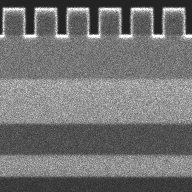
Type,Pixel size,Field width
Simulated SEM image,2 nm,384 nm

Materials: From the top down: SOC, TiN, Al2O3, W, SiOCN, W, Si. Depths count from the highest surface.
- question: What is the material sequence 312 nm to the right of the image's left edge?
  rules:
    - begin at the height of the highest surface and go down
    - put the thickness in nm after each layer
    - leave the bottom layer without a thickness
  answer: empty 54, Al2O3 88, W 90, SiOCN 62, W 44, Si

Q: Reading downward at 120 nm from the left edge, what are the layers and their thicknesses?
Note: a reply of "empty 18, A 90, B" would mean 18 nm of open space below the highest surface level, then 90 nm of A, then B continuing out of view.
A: empty 54, Al2O3 88, W 90, SiOCN 62, W 44, Si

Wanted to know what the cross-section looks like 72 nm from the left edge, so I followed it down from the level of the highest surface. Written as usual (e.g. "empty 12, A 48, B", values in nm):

SOC 14, TiN 40, Al2O3 88, W 90, SiOCN 62, W 44, Si